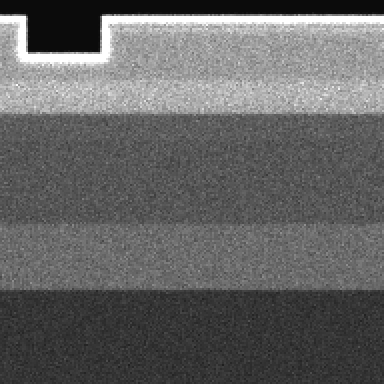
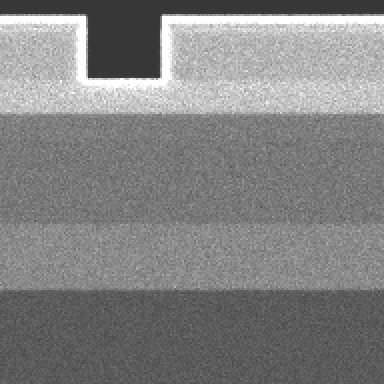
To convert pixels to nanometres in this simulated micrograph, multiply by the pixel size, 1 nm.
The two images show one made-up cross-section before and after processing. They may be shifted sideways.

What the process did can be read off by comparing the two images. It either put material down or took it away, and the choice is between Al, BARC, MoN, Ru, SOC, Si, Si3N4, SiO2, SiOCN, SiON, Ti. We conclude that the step removed SiO2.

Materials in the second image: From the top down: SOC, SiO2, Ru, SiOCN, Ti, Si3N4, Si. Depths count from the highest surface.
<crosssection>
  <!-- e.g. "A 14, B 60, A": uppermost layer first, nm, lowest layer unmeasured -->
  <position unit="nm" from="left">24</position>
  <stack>SOC 12, SiO2 52, Ru 34, SiOCN 26, Ti 84, Si3N4 66, Si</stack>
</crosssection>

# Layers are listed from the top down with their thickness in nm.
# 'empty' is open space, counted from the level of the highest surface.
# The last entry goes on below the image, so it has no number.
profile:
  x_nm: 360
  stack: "SOC 12, SiO2 52, Ru 34, SiOCN 26, Ti 84, Si3N4 66, Si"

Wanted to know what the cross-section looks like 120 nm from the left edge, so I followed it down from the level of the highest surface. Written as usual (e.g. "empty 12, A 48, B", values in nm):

empty 64, Ru 34, SiOCN 26, Ti 84, Si3N4 66, Si